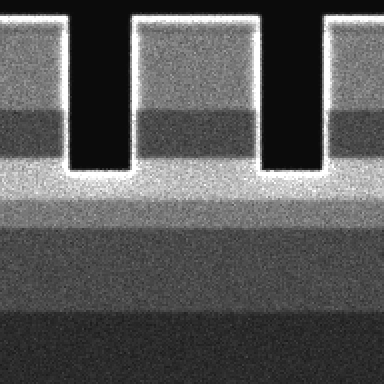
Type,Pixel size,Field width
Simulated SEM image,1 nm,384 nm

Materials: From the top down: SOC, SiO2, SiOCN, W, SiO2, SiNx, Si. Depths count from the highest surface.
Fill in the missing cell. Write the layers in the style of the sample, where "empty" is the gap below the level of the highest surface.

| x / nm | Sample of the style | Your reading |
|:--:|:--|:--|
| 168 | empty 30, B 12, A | SOC 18, SiO2 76, SiOCN 48, W 42, SiO2 28, SiNx 84, Si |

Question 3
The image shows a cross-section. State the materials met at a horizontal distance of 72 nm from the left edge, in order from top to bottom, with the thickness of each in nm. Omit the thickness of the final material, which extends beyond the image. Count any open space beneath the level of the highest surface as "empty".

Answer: empty 156, W 28, SiO2 28, SiNx 84, Si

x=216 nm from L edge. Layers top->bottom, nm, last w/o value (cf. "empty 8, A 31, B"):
SOC 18, SiO2 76, SiOCN 48, W 42, SiO2 28, SiNx 84, Si